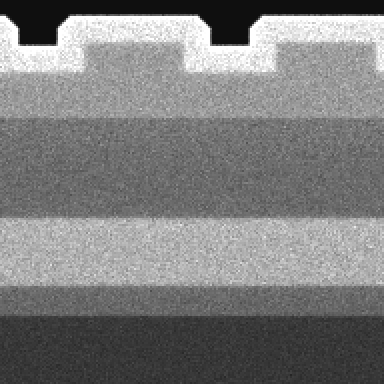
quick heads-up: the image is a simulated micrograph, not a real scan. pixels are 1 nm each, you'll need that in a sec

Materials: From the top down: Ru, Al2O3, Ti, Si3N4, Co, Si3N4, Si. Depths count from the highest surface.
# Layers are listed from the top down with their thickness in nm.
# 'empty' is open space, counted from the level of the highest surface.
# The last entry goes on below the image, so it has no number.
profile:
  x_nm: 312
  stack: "Ru 26, Al2O3 76, Ti 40, Si3N4 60, Co 68, Si3N4 30, Si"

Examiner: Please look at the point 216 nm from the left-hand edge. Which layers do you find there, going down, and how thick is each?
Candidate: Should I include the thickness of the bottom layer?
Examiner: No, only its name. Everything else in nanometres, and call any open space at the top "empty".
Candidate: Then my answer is empty 30, Ru 26, Al2O3 46, Ti 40, Si3N4 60, Co 68, Si3N4 30, Si